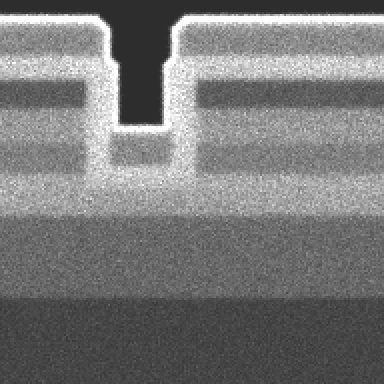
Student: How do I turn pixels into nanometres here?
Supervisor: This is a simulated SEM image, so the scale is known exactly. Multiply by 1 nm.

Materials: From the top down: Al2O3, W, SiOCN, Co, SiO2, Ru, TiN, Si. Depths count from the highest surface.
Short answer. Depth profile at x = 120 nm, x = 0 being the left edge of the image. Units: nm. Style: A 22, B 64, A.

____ empty 110, Al2O3 40, W 24, Ru 26, TiN 82, Si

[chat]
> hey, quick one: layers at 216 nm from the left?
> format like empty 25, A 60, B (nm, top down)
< Al2O3 40, W 24, SiOCN 28, Co 36, SiO2 30, Ru 42, TiN 82, Si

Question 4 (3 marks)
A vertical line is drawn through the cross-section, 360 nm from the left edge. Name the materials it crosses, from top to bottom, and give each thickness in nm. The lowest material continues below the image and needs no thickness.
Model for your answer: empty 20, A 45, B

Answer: Al2O3 40, W 24, SiOCN 28, Co 36, SiO2 30, Ru 42, TiN 82, Si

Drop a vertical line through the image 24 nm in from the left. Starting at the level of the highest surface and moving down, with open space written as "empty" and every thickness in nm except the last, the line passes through Al2O3 40, W 24, SiOCN 28, Co 36, SiO2 30, Ru 42, TiN 82, Si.